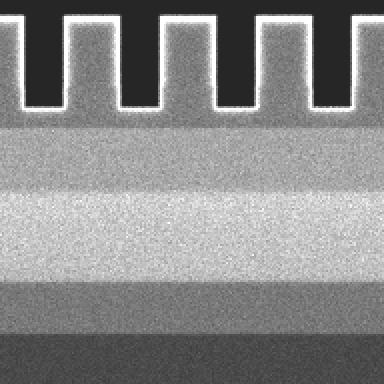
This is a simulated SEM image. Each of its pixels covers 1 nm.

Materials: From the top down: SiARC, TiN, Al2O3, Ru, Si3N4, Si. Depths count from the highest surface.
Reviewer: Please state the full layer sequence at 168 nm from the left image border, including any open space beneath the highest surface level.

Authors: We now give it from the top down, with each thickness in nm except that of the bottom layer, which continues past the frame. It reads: SiARC 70, TiN 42, Al2O3 64, Ru 90, Si3N4 52, Si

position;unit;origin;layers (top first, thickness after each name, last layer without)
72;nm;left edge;SiARC 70, TiN 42, Al2O3 64, Ru 90, Si3N4 52, Si